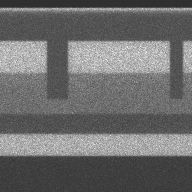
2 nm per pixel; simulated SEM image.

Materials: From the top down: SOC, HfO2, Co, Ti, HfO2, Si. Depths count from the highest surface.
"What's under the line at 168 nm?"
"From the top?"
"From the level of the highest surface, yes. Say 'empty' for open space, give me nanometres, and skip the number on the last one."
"SOC 66, HfO2 64, Co 82, Ti 40, HfO2 44, Si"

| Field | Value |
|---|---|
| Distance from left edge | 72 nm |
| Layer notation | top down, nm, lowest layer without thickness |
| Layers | SOC 66, HfO2 64, Co 82, Ti 40, HfO2 44, Si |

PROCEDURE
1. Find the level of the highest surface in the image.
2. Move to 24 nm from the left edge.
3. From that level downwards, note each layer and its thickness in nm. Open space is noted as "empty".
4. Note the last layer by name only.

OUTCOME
SOC 66, HfO2 64, Co 82, Ti 40, HfO2 44, Si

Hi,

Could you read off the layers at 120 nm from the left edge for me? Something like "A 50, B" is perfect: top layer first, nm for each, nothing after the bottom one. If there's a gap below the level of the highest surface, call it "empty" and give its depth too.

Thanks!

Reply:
SOC 182, Co 30, Ti 40, HfO2 44, Si